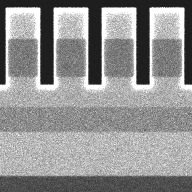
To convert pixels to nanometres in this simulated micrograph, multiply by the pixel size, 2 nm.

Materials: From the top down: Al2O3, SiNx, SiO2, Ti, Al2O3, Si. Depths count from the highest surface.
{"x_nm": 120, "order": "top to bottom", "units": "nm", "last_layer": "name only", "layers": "Al2O3 62, SiNx 76, SiO2 60, Ti 50, Al2O3 88, Si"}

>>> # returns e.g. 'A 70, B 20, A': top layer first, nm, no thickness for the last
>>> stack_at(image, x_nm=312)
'Al2O3 62, SiNx 76, SiO2 60, Ti 50, Al2O3 88, Si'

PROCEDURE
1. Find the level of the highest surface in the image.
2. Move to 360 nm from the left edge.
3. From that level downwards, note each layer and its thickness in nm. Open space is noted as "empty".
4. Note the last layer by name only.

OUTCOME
Al2O3 62, SiNx 76, SiO2 60, Ti 50, Al2O3 88, Si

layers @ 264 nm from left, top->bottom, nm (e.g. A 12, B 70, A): Al2O3 62, SiNx 76, SiO2 60, Ti 50, Al2O3 88, Si